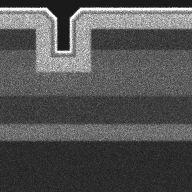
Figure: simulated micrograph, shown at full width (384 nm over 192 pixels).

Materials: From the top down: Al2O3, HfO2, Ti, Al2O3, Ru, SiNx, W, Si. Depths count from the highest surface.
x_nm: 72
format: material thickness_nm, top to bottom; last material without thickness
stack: Al2O3 12, HfO2 116, Ru 48, SiNx 56, W 34, Si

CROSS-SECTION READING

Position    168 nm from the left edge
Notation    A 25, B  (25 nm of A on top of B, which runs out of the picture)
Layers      Al2O3 12, HfO2 116, Ru 48, SiNx 56, W 34, Si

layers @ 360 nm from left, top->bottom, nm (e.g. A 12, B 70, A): Al2O3 12, HfO2 30, Ti 42, Al2O3 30, Ru 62, SiNx 56, W 34, Si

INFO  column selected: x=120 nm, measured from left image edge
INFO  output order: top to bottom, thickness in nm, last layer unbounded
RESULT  empty 86, Al2O3 12, HfO2 30, Ru 48, SiNx 56, W 34, Si